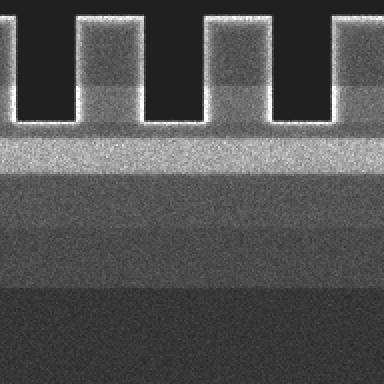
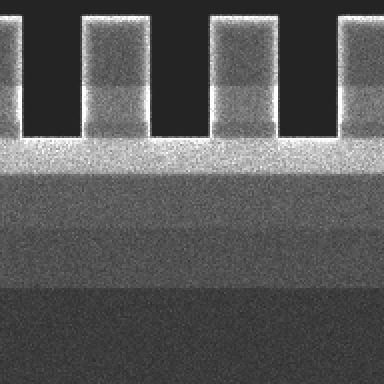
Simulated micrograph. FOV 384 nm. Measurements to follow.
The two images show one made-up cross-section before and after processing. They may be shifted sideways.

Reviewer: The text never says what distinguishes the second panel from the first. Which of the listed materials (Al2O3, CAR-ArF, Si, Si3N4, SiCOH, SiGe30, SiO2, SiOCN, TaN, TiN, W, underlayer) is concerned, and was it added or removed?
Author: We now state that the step removed TiN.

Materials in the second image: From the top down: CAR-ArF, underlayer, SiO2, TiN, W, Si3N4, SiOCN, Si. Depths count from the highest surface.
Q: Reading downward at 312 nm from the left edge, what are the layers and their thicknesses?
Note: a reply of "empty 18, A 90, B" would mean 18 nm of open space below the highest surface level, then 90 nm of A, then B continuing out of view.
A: empty 122, W 36, Si3N4 54, SiOCN 60, Si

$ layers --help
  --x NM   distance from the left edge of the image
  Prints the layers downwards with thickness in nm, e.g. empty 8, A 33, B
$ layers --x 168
empty 122, W 36, Si3N4 54, SiOCN 60, Si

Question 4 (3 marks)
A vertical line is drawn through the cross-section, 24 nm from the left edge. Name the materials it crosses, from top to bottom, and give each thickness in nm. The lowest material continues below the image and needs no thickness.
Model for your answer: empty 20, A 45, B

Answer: empty 122, W 36, Si3N4 54, SiOCN 60, Si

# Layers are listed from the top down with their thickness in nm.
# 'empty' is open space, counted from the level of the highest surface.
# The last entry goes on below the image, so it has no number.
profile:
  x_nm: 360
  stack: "CAR-ArF 38, underlayer 32, SiO2 36, TiN 16, W 36, Si3N4 54, SiOCN 60, Si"